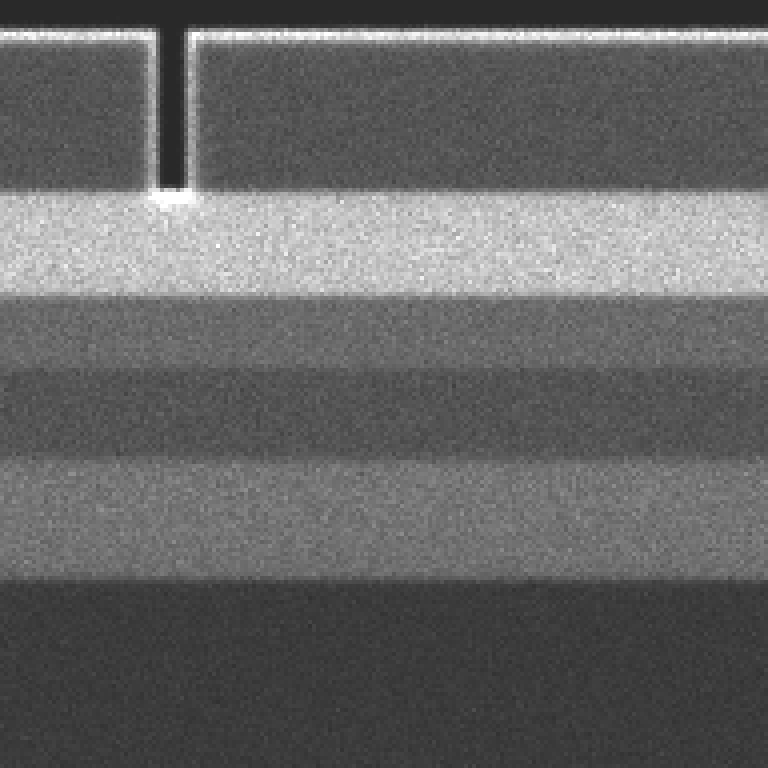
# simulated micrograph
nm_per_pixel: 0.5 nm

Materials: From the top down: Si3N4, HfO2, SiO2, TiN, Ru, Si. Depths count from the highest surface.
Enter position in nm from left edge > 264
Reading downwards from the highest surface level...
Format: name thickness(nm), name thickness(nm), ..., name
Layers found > Si3N4 80, HfO2 52, SiO2 36, TiN 46, Ru 60, Si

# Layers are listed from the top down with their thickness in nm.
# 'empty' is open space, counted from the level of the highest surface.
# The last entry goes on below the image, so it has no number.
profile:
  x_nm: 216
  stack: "Si3N4 80, HfO2 52, SiO2 36, TiN 46, Ru 60, Si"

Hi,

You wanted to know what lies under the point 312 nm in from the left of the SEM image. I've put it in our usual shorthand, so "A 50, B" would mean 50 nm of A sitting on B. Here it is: Si3N4 80, HfO2 52, SiO2 36, TiN 46, Ru 60, Si